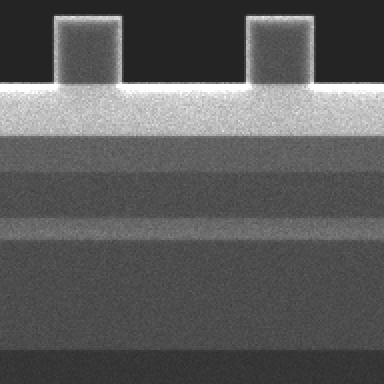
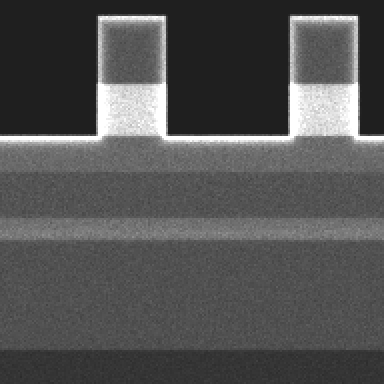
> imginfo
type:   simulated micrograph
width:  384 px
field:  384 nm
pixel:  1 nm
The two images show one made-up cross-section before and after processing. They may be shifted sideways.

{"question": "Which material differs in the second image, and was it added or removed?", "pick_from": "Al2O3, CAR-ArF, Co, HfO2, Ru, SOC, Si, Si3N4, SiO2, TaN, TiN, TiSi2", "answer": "HfO2, removed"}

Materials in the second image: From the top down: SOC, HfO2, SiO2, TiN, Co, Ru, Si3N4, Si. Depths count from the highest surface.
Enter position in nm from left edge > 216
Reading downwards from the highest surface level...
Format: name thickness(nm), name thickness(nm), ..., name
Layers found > empty 120, SiO2 36, TiN 46, Co 12, Ru 10, Si3N4 110, Si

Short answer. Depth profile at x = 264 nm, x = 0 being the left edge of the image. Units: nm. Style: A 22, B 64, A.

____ empty 120, SiO2 36, TiN 46, Co 12, Ru 10, Si3N4 110, Si